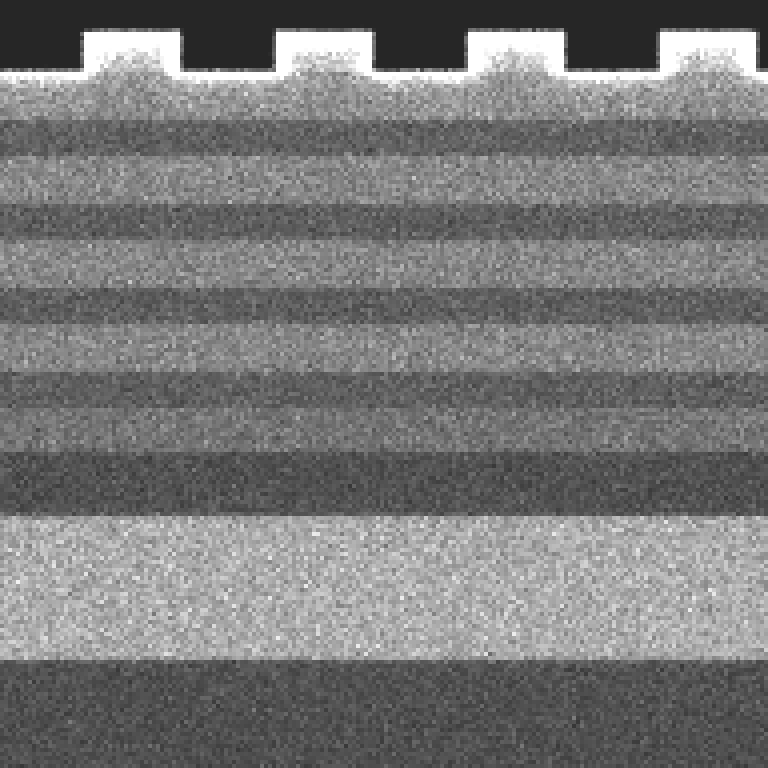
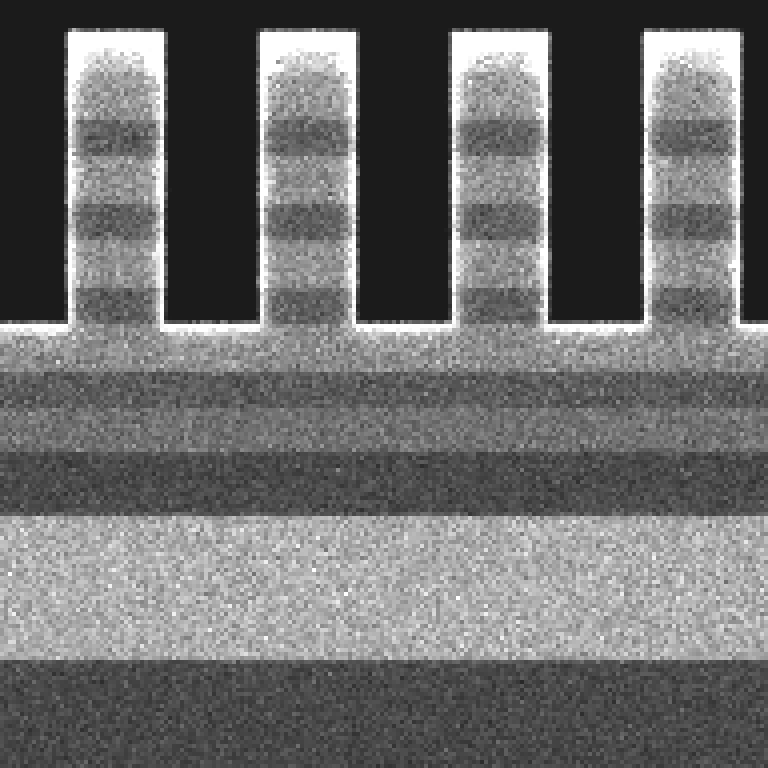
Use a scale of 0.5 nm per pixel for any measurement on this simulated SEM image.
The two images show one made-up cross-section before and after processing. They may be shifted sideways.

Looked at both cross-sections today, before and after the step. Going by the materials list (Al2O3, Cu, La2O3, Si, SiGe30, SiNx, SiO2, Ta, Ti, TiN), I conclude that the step removed SiGe30 and TiN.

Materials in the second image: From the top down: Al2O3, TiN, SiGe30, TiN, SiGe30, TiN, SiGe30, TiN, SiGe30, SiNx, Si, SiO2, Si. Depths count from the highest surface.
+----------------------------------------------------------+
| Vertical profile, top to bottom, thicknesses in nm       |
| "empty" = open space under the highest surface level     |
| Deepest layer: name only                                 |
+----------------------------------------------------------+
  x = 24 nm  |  empty 146, TiN 24, SiGe30 18, SiNx 22, Si 32, SiO2 72, Si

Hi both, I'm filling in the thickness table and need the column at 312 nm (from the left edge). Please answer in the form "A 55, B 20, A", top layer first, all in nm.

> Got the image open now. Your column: empty 146, TiN 24, SiGe30 18, SiNx 22, Si 32, SiO2 72, Si